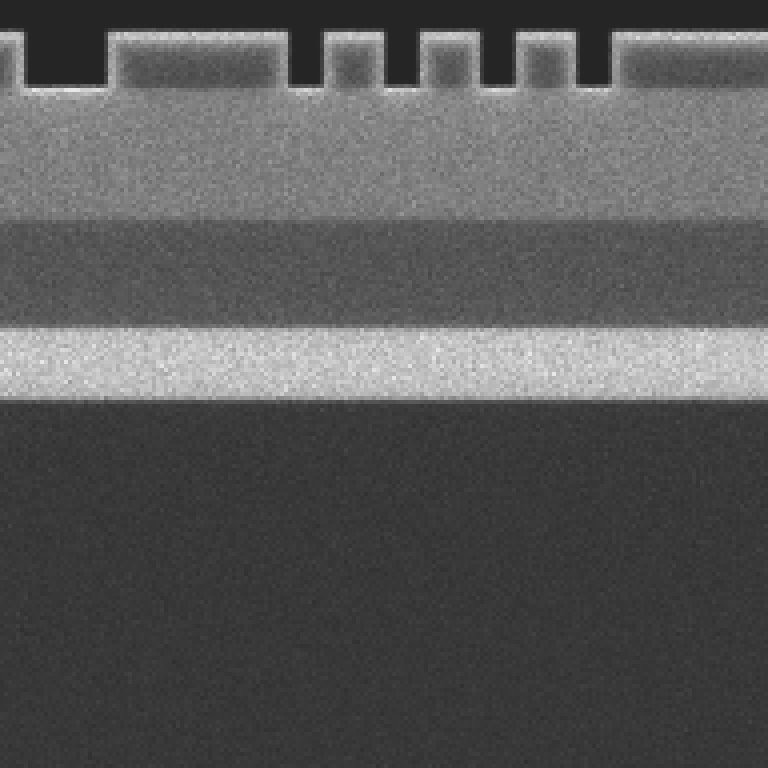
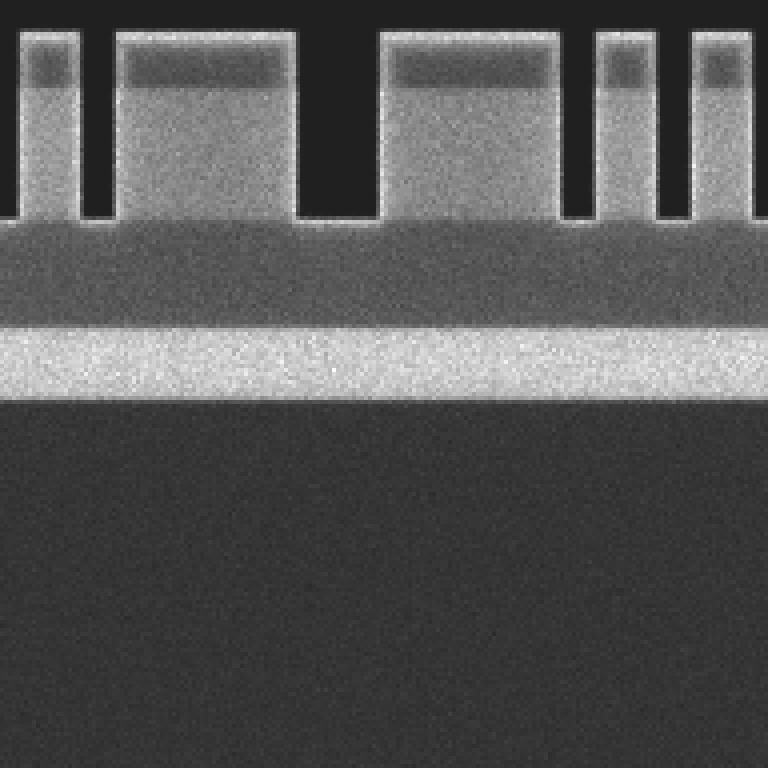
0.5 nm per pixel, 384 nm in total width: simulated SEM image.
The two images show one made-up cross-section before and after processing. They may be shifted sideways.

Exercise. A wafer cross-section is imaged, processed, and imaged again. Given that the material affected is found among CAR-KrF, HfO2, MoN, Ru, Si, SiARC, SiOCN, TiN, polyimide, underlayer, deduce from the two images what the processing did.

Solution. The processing removed Ru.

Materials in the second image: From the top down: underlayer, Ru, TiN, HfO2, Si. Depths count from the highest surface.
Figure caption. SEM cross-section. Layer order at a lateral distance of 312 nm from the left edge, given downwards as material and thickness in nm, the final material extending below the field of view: underlayer 28, Ru 66, TiN 54, HfO2 36, Si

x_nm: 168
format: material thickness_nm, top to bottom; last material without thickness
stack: empty 94, TiN 54, HfO2 36, Si